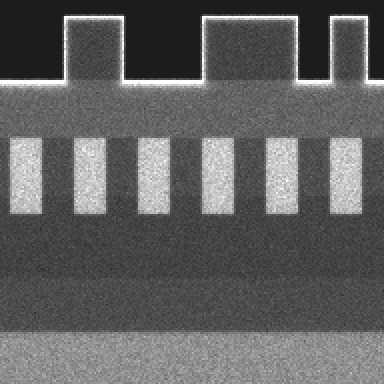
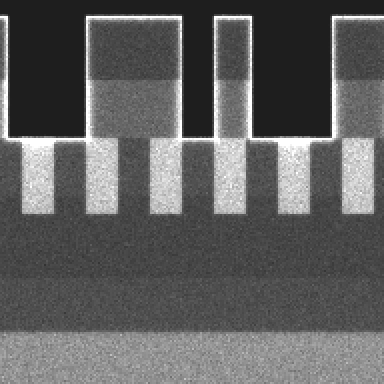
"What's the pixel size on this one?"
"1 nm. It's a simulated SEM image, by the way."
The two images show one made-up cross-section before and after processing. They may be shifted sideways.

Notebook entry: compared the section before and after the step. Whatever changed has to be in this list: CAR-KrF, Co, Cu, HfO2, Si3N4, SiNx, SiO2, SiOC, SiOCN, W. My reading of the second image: SiO2 removed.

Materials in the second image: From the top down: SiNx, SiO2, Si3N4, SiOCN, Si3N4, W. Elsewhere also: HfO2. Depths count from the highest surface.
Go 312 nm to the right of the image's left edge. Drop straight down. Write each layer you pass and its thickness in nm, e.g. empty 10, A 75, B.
empty 122, Si3N4 58, SiOCN 82, Si3N4 54, W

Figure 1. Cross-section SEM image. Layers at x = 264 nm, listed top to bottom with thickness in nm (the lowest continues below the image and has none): empty 122, Si3N4 58, SiOCN 82, Si3N4 54, W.